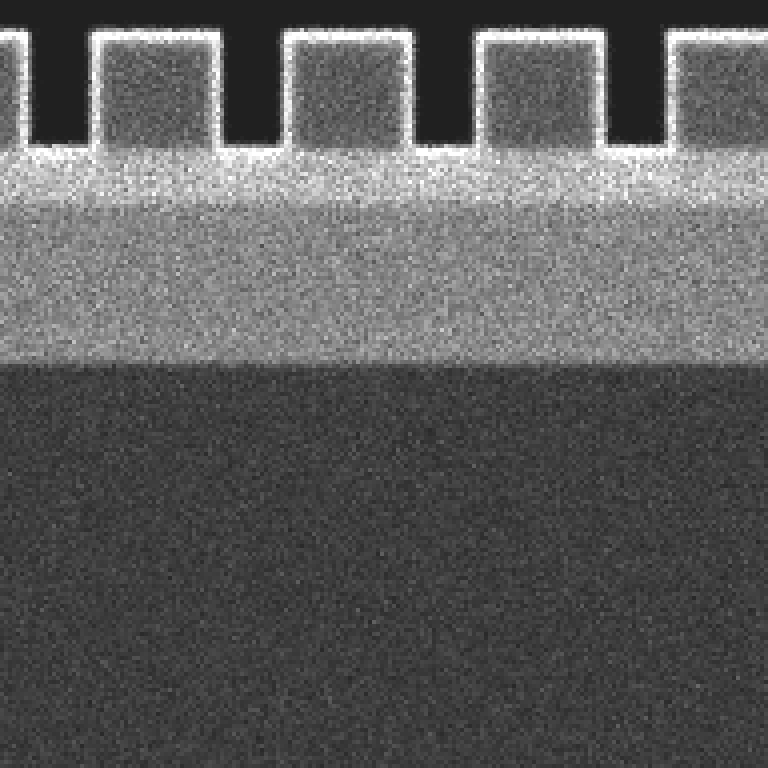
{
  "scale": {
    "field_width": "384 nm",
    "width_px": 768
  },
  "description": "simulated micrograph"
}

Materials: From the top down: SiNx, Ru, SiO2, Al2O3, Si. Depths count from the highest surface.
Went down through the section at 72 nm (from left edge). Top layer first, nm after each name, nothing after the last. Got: SiNx 58, Ru 28, SiO2 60, Al2O3 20, Si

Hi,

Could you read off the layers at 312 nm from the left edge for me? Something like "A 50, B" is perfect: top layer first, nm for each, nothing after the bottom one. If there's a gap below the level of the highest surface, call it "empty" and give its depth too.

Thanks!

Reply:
empty 58, Ru 28, SiO2 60, Al2O3 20, Si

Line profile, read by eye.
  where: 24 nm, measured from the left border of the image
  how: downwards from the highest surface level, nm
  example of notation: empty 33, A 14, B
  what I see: empty 58, Ru 28, SiO2 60, Al2O3 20, Si